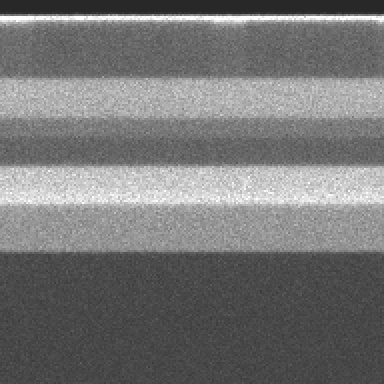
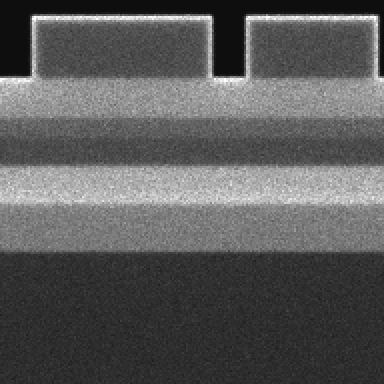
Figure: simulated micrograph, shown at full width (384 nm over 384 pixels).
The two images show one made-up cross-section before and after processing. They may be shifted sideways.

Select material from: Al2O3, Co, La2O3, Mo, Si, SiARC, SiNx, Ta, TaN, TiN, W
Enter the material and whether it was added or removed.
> SiARC / removed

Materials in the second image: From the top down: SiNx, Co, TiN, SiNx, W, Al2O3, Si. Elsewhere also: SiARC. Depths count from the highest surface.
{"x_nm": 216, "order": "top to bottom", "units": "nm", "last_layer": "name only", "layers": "empty 62, Co 40, TiN 20, SiNx 28, W 38, Al2O3 48, Si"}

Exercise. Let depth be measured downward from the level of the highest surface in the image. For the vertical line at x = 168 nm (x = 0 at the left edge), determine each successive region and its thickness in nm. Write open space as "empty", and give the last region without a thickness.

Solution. SiNx 62, Co 40, TiN 20, SiNx 28, W 38, Al2O3 48, Si